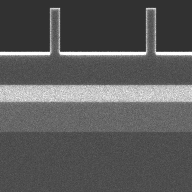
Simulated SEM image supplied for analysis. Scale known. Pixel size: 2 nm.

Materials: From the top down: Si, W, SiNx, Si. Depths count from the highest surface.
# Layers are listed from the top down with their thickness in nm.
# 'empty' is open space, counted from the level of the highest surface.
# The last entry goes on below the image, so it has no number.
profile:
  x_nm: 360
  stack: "empty 88, Si 66, W 34, SiNx 60, Si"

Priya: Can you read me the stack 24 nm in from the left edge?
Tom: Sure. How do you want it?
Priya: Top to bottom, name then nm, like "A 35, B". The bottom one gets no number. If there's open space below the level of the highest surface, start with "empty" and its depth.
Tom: empty 88, Si 66, W 34, SiNx 60, Si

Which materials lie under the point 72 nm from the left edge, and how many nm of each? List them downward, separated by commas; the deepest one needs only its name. empty 88, Si 66, W 34, SiNx 60, Si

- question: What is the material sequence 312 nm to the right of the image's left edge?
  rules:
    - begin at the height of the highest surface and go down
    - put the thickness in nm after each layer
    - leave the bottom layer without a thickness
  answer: empty 88, Si 66, W 34, SiNx 60, Si